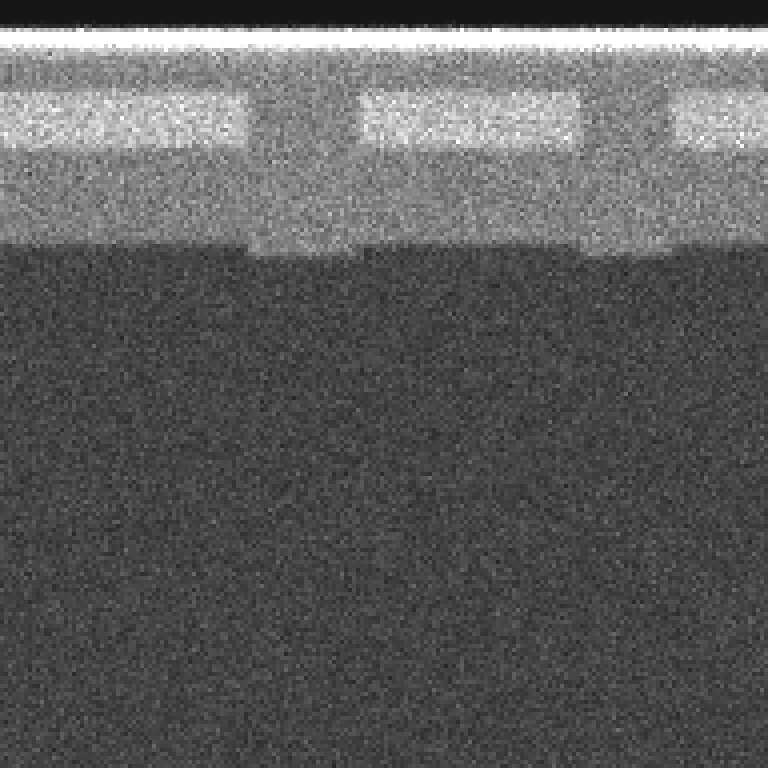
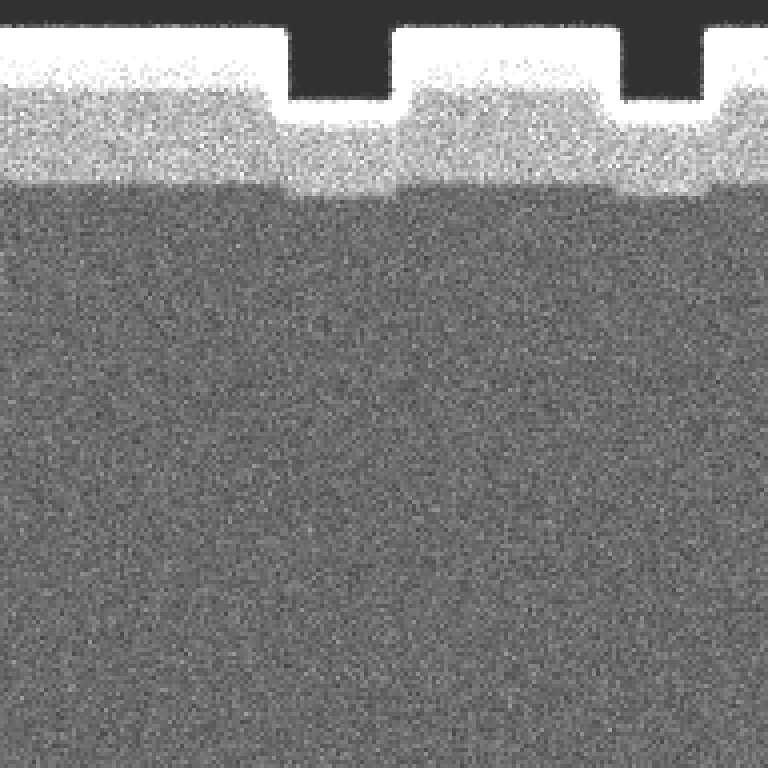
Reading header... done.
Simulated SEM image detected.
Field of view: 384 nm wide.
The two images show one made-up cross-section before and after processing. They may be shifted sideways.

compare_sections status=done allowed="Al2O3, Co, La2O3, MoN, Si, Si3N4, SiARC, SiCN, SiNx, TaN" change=removed material="SiARC"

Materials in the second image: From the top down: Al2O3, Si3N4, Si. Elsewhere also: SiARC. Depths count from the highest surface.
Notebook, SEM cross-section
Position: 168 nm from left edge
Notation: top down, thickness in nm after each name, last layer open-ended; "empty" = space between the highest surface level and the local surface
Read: empty 36, SiARC 46, Si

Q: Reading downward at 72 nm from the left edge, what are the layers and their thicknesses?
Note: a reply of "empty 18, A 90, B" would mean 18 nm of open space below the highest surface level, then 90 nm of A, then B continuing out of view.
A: Al2O3 28, Si3N4 48, Si